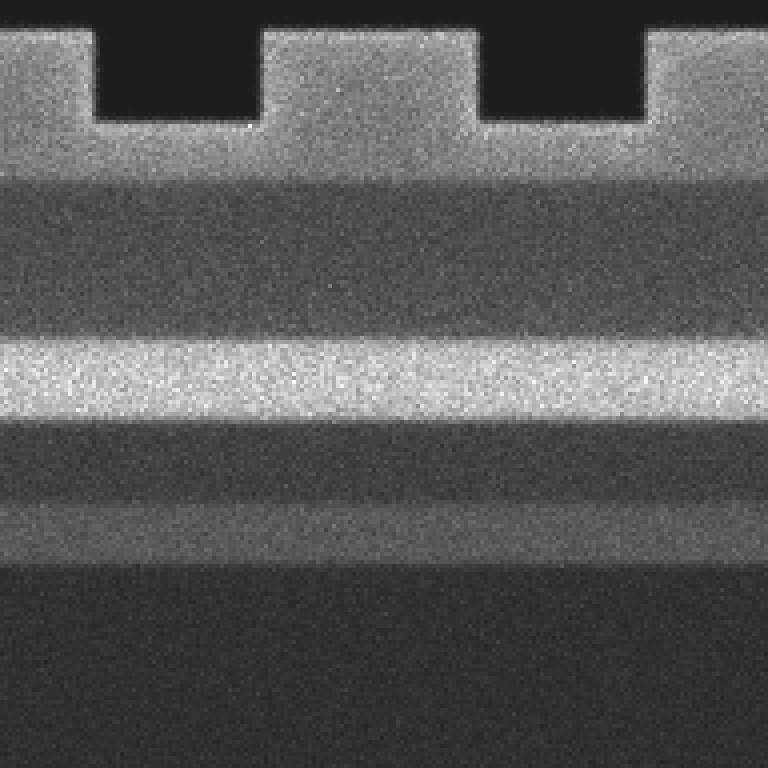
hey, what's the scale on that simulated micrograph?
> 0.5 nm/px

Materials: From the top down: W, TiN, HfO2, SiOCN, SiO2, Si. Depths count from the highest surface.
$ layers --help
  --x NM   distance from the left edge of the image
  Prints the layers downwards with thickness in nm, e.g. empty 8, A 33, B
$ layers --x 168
W 74, TiN 80, HfO2 40, SiOCN 42, SiO2 30, Si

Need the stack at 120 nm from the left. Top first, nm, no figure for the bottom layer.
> empty 46, W 28, TiN 80, HfO2 40, SiOCN 42, SiO2 30, Si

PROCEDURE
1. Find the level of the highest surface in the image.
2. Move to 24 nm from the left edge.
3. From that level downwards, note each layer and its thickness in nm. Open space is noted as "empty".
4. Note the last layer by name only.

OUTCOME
W 74, TiN 80, HfO2 40, SiOCN 42, SiO2 30, Si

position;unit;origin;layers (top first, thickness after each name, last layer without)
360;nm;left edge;W 74, TiN 80, HfO2 40, SiOCN 42, SiO2 30, Si